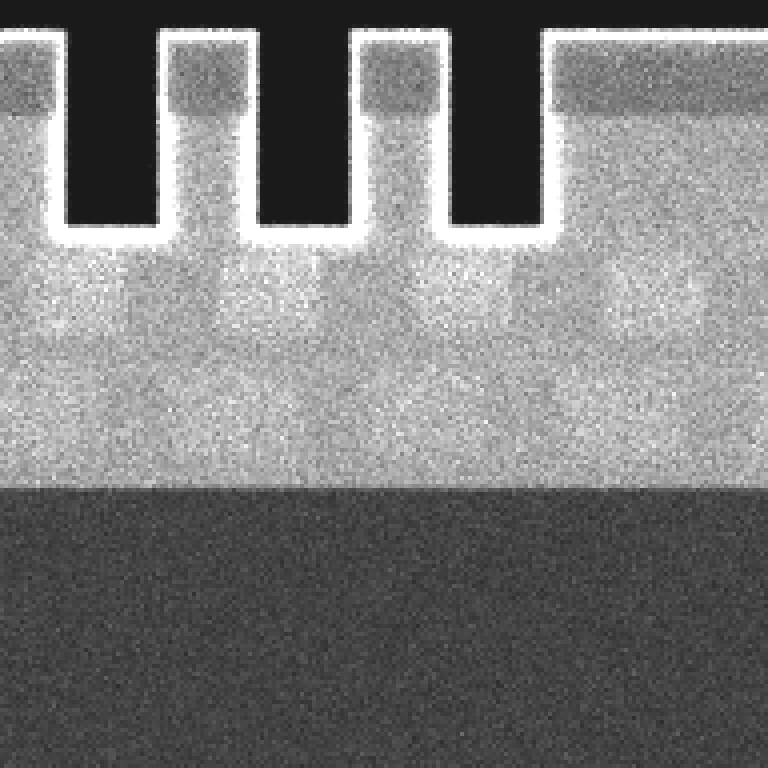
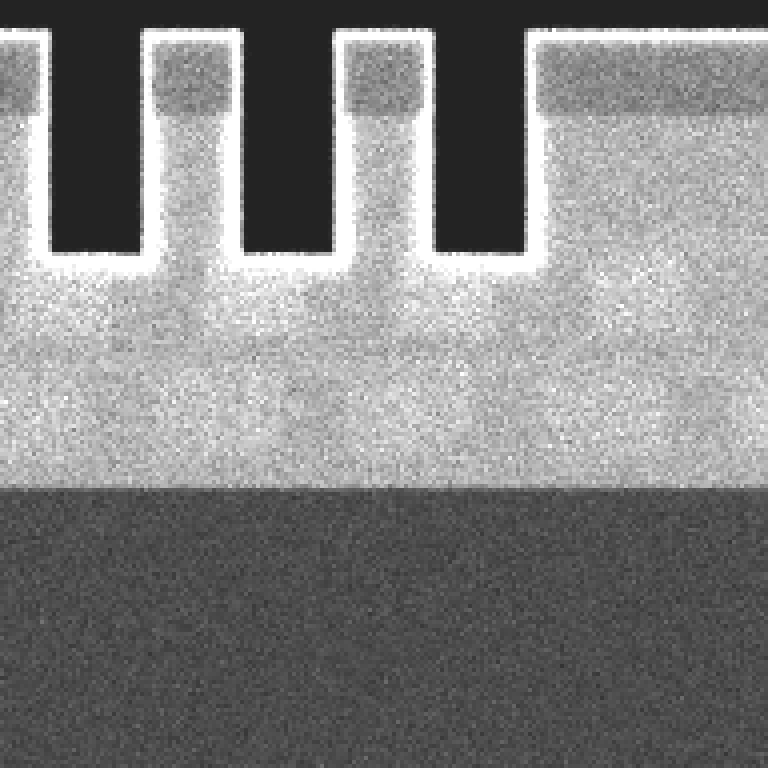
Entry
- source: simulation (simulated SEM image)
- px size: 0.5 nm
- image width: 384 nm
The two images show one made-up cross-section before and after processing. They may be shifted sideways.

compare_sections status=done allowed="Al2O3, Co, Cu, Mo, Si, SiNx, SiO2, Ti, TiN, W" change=removed material="Al2O3"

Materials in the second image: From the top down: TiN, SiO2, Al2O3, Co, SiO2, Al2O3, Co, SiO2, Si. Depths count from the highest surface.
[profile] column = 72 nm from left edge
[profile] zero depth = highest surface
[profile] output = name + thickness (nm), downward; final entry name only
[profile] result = TiN 42, SiO2 56, Al2O3 14, SiO2 52, Al2O3 8, SiO2 56, Si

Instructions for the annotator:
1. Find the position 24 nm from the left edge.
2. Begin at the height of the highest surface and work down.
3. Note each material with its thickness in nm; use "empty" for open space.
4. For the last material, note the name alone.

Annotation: empty 112, Co 40, SiO2 12, Al2O3 8, Co 42, SiO2 14, Si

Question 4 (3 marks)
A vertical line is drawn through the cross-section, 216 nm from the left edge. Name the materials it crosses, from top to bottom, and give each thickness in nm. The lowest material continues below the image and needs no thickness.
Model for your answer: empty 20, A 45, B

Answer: empty 112, Co 40, SiO2 12, Al2O3 8, Co 42, SiO2 14, Si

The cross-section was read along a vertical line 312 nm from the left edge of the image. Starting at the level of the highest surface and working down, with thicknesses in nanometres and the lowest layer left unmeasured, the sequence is TiN 42, SiO2 56, Al2O3 14, Co 40, SiO2 12, Al2O3 8, Co 42, SiO2 14, Si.